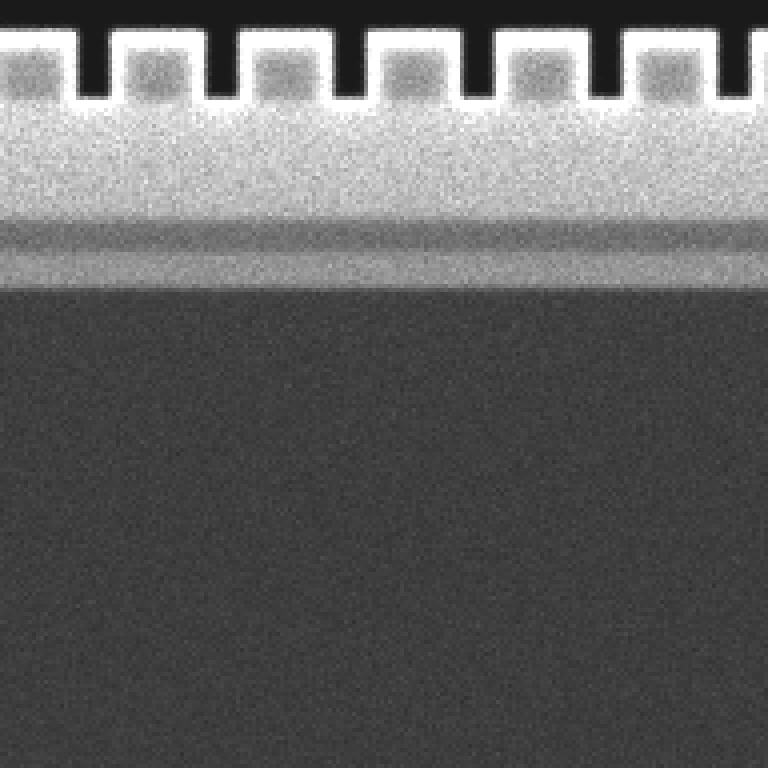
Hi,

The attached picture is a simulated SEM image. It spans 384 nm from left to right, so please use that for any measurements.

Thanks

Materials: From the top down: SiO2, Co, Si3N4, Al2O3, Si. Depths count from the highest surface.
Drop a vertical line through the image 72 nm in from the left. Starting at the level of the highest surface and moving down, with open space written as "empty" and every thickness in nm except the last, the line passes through SiO2 34, Co 60, Si3N4 16, Al2O3 18, Si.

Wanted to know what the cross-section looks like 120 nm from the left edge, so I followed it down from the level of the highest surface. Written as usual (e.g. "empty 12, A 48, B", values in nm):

SiO2 34, Co 60, Si3N4 16, Al2O3 18, Si